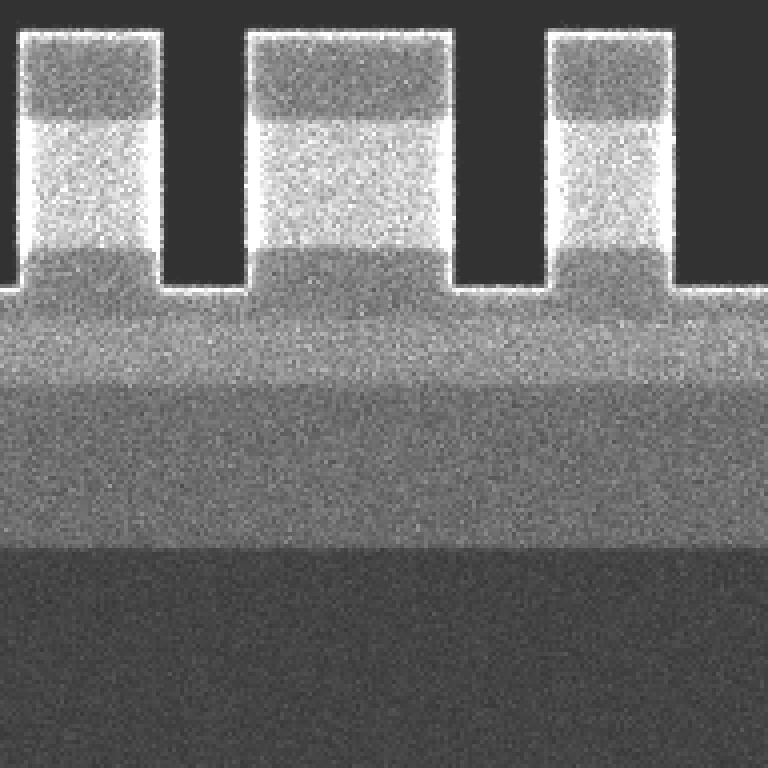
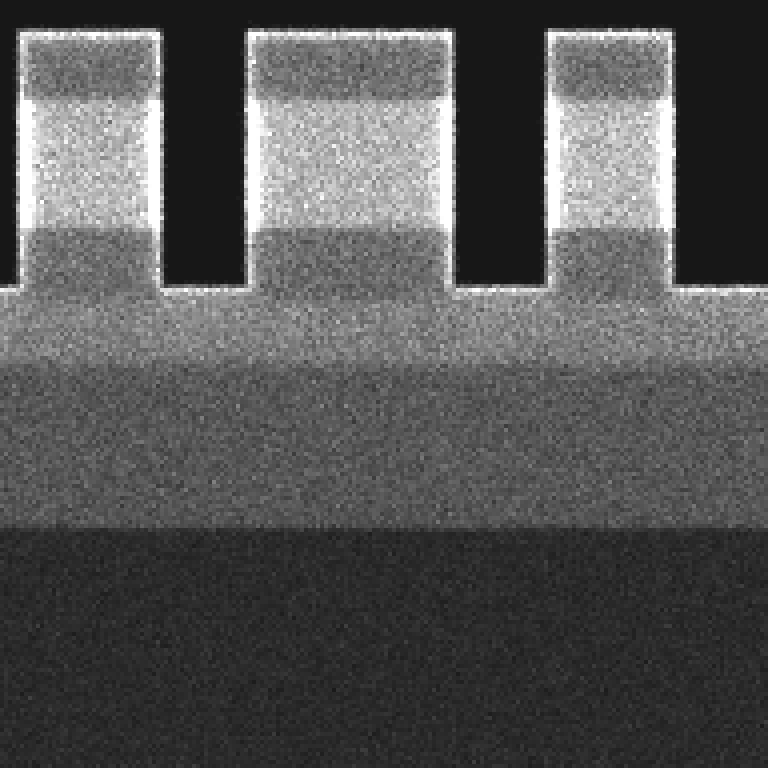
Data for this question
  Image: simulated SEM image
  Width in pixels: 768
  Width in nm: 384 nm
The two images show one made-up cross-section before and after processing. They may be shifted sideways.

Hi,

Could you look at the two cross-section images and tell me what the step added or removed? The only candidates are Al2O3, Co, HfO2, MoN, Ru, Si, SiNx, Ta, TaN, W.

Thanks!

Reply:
removed Ru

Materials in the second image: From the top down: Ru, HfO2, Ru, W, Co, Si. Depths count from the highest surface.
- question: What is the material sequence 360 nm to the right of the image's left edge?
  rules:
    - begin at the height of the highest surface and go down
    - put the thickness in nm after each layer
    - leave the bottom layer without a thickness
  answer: empty 128, Ru 6, W 32, Co 82, Si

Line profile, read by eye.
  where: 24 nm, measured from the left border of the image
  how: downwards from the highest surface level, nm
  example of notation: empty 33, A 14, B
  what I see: Ru 34, HfO2 64, Ru 36, W 32, Co 82, Si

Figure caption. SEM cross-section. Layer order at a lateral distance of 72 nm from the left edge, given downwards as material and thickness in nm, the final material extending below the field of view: Ru 34, HfO2 64, Ru 36, W 32, Co 82, Si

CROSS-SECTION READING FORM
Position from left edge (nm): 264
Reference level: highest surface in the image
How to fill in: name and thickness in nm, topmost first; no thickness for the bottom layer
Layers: empty 128, Ru 6, W 32, Co 82, Si